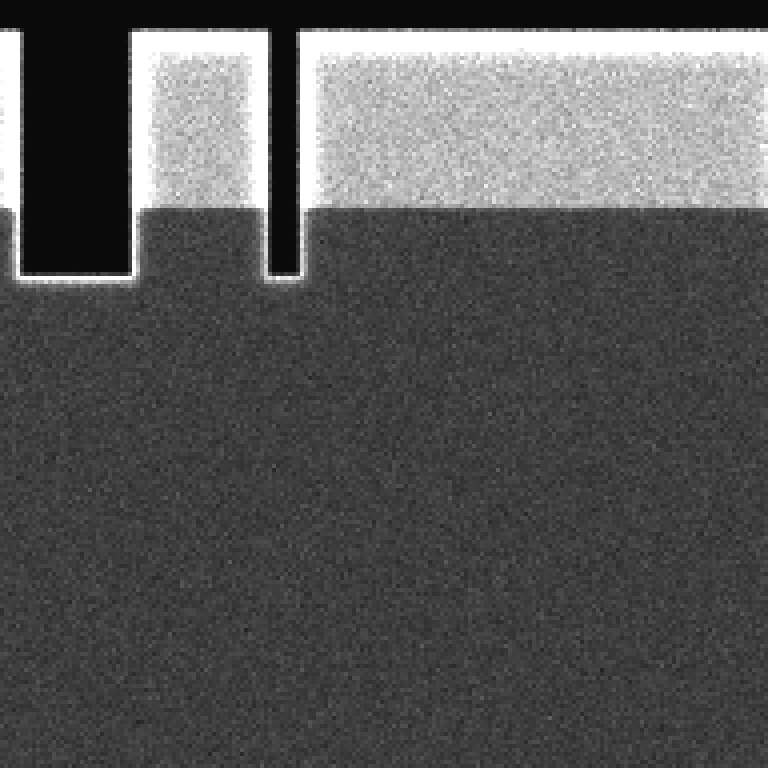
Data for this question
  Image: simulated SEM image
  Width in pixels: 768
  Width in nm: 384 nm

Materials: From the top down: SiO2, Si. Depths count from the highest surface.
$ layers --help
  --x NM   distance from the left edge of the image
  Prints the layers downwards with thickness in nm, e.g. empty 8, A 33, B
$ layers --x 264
SiO2 88, Si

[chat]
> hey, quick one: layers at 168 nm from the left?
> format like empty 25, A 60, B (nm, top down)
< SiO2 88, Si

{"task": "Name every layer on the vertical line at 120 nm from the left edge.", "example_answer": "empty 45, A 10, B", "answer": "SiO2 88, Si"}